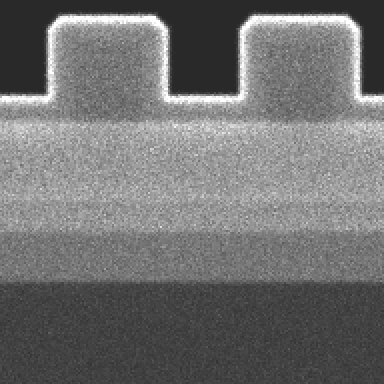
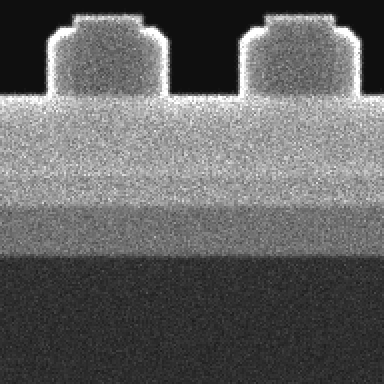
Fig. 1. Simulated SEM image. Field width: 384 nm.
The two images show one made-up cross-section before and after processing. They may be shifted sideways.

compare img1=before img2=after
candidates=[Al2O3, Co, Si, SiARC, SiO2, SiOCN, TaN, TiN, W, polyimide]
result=removed:Al2O3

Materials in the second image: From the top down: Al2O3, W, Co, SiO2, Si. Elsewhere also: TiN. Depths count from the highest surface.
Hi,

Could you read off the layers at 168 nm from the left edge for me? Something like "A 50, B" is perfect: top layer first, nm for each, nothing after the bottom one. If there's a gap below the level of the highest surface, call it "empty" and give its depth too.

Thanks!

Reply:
empty 80, W 80, Co 30, SiO2 50, Si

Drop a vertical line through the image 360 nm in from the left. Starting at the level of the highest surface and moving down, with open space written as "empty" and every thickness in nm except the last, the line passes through empty 80, W 80, Co 30, SiO2 50, Si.